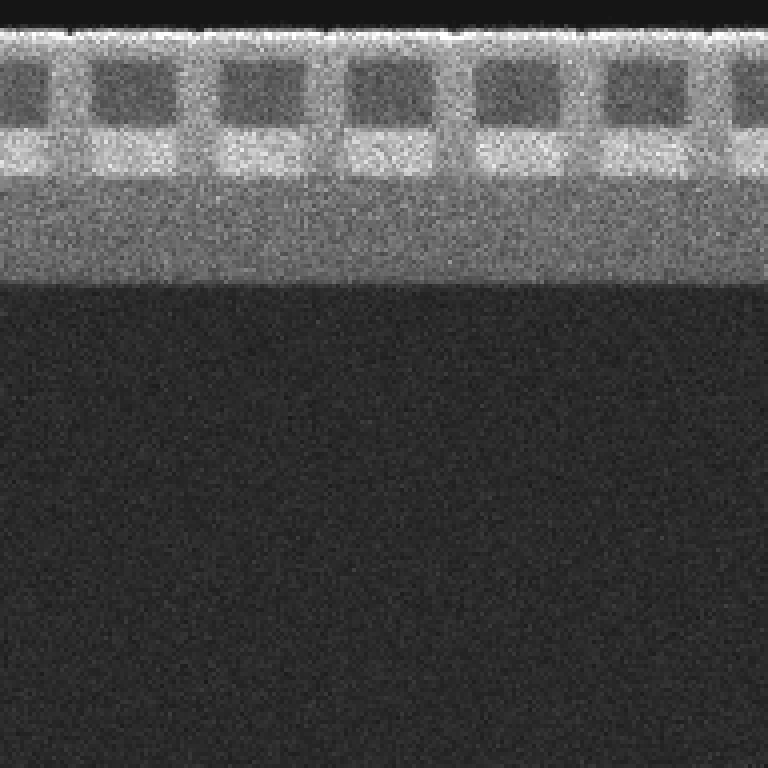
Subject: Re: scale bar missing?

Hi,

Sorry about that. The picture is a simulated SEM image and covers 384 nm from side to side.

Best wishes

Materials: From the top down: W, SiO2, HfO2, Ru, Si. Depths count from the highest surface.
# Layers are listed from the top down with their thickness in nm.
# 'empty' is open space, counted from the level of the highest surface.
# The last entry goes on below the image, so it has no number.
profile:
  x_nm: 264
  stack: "W 14, SiO2 34, HfO2 24, Ru 54, Si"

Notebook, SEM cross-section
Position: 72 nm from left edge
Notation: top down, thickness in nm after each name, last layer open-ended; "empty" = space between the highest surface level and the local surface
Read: W 14, SiO2 34, HfO2 24, Ru 54, Si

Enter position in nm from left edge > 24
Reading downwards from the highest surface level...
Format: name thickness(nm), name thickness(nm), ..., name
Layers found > W 72, Ru 54, Si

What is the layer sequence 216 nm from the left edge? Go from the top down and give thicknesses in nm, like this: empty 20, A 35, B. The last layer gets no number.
W 72, Ru 54, Si